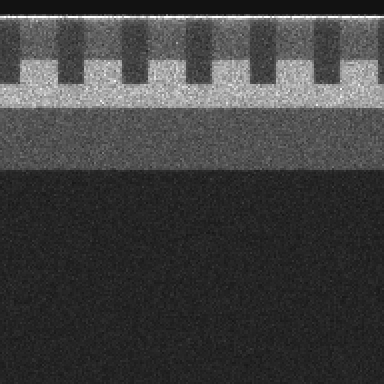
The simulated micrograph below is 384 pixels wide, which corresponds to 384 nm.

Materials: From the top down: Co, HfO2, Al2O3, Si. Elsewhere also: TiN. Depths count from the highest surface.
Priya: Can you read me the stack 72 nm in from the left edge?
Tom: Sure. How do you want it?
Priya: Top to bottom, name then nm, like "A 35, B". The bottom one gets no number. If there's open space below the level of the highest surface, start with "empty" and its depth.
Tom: TiN 68, HfO2 24, Al2O3 62, Si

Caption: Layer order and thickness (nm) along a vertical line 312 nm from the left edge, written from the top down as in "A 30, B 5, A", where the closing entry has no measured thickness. Co 44, HfO2 48, Al2O3 62, Si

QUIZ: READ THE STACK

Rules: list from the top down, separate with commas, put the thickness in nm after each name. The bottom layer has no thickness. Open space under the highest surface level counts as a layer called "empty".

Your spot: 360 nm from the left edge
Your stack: Co 44, HfO2 48, Al2O3 62, Si